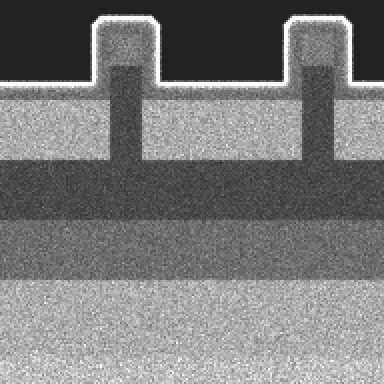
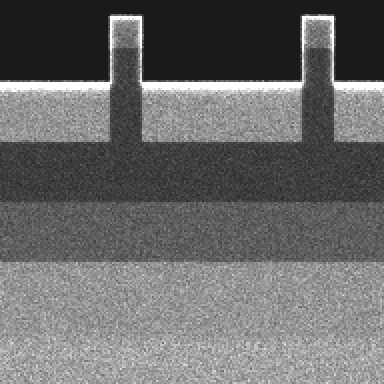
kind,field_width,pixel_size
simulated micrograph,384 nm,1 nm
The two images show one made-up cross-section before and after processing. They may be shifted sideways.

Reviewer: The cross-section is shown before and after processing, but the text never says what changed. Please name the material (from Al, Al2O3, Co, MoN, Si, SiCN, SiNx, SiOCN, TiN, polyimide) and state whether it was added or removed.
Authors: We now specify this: SiOCN, removed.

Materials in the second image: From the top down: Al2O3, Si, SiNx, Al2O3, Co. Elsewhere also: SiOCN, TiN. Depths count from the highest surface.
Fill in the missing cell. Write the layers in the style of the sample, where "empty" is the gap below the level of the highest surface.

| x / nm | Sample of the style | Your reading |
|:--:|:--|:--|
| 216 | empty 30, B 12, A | empty 66, Al2O3 60, Si 60, SiNx 60, Al2O3 76, Co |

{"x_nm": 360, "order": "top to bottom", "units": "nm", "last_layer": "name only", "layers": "empty 66, Al2O3 60, Si 60, SiNx 60, Al2O3 76, Co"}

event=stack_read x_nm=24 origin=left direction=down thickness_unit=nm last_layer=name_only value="empty 66, Al2O3 60, Si 60, SiNx 60, Al2O3 76, Co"